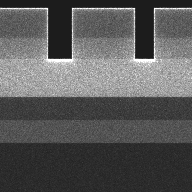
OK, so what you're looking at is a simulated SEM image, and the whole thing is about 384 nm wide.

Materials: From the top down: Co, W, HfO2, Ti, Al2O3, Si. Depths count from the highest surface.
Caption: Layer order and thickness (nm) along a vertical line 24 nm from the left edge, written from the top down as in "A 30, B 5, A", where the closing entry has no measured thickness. Co 60, W 42, HfO2 76, Ti 46, Al2O3 46, Si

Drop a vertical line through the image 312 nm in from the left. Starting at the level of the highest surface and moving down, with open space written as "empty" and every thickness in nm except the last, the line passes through Co 60, W 42, HfO2 76, Ti 46, Al2O3 46, Si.